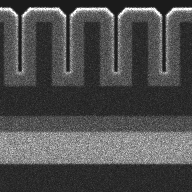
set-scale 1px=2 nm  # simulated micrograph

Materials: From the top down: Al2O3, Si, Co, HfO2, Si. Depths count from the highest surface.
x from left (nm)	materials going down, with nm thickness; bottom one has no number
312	empty 4, Al2O3 152, Si 60, Co 32, HfO2 64, Si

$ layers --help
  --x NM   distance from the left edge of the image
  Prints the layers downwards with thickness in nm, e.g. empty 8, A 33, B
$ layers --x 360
Al2O3 28, Si 188, Co 32, HfO2 64, Si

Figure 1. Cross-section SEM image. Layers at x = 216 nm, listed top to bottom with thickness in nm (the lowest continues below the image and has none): empty 4, Al2O3 152, Si 60, Co 32, HfO2 64, Si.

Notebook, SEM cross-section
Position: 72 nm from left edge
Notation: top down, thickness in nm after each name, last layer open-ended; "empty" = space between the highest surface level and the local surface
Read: Al2O3 28, Si 188, Co 32, HfO2 64, Si